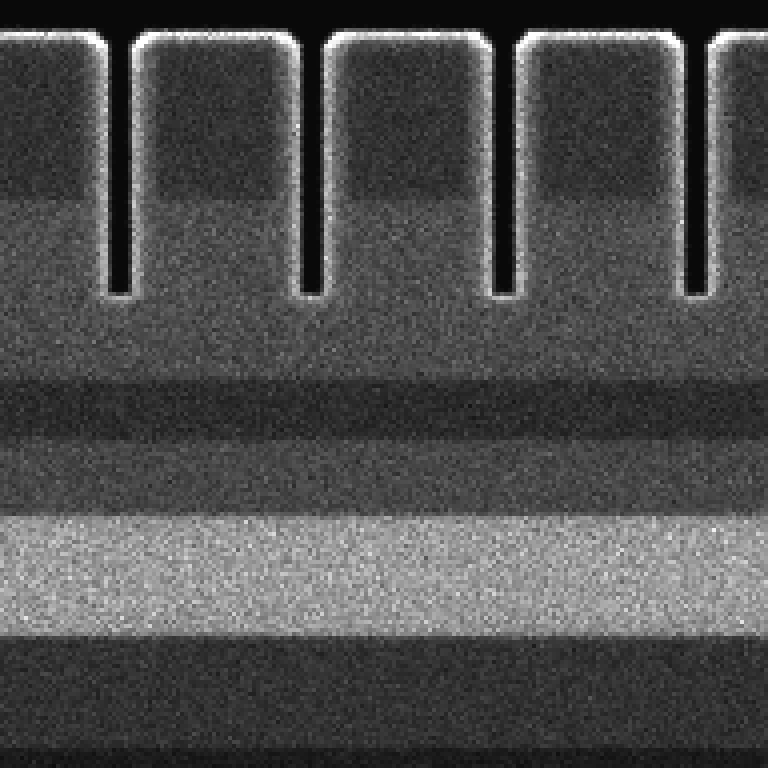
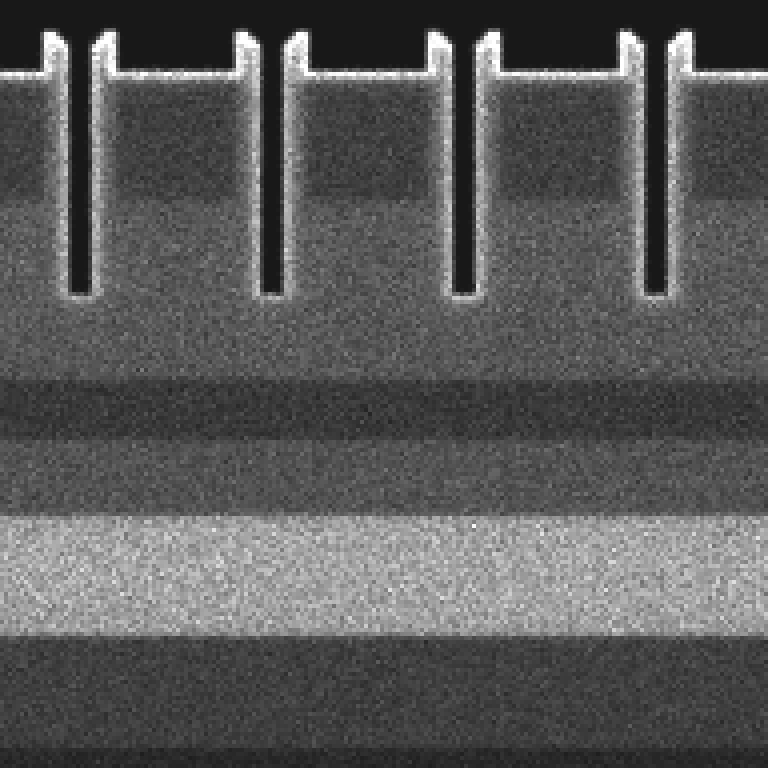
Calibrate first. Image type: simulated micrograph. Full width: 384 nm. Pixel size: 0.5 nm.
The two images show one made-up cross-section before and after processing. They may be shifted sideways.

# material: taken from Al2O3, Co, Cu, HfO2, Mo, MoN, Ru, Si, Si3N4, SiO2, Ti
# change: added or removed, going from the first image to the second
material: Si3N4
change: removed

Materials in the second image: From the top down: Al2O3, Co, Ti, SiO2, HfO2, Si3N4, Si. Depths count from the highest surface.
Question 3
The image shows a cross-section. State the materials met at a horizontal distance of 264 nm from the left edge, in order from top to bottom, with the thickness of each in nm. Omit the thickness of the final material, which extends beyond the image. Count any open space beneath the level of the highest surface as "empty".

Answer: empty 20, Si3N4 64, Co 90, Ti 30, SiO2 38, HfO2 60, Si3N4 56, Si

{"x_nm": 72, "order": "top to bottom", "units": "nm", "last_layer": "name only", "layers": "empty 20, Si3N4 64, Co 90, Ti 30, SiO2 38, HfO2 60, Si3N4 56, Si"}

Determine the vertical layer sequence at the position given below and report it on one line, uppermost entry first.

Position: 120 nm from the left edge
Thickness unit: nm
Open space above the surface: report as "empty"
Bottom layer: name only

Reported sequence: Al2O3 132, Co 42, Ti 30, SiO2 38, HfO2 60, Si3N4 56, Si